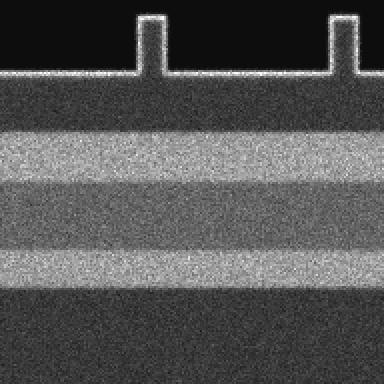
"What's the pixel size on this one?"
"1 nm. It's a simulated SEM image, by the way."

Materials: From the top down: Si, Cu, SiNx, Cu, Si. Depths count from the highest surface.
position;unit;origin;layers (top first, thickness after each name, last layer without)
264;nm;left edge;empty 56, Si 60, Cu 50, SiNx 68, Cu 38, Si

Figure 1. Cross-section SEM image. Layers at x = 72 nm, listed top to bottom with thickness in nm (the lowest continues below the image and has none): empty 56, Si 60, Cu 50, SiNx 68, Cu 38, Si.